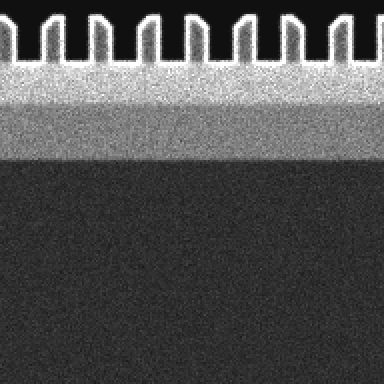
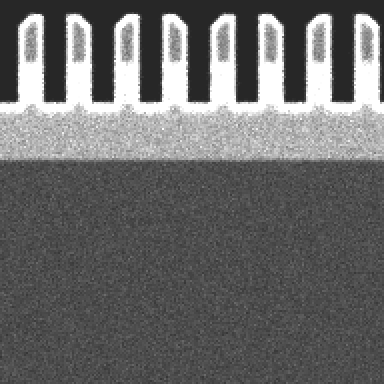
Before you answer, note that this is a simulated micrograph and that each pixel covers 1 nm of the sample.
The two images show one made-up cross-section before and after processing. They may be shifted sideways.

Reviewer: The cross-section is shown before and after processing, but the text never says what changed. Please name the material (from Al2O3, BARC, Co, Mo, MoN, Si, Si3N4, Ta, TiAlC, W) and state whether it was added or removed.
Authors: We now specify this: W, removed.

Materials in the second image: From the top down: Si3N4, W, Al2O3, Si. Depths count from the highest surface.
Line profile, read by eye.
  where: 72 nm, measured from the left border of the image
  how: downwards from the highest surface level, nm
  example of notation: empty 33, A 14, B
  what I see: Si3N4 46, W 42, Al2O3 56, Si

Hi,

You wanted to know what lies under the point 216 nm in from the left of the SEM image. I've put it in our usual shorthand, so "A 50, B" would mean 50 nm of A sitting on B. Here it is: empty 6, Si3N4 40, W 42, Al2O3 56, Si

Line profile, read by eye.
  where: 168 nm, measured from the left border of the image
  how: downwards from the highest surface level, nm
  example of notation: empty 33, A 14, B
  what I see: Si3N4 46, W 42, Al2O3 56, Si